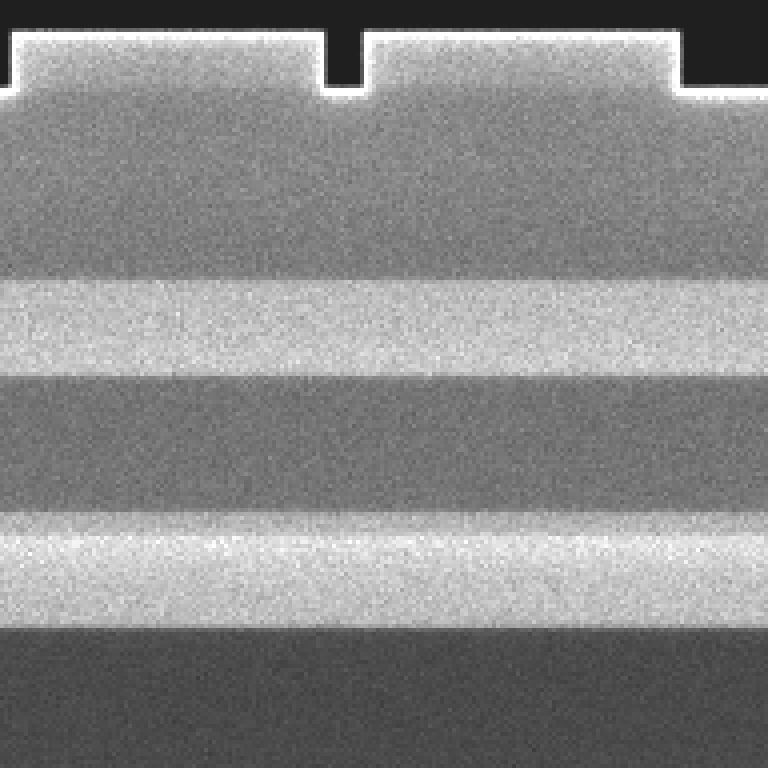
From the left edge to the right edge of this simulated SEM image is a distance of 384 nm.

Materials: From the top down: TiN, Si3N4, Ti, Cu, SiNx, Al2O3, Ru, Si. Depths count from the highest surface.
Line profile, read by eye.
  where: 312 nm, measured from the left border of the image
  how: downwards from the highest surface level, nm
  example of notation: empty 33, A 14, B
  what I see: TiN 28, Si3N4 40, Ti 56, Cu 48, SiNx 68, Al2O3 12, Ru 46, Si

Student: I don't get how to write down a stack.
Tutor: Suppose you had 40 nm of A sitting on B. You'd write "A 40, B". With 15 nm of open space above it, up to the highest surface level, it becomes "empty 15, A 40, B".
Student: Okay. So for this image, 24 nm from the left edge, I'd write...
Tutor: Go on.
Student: TiN 28, Si3N4 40, Ti 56, Cu 48, SiNx 68, Al2O3 12, Ru 46, Si